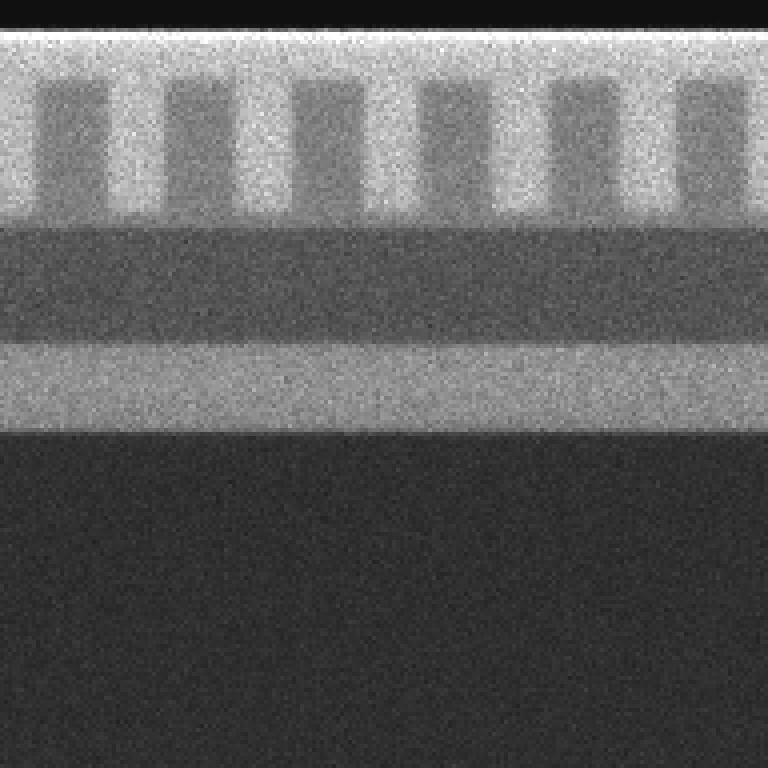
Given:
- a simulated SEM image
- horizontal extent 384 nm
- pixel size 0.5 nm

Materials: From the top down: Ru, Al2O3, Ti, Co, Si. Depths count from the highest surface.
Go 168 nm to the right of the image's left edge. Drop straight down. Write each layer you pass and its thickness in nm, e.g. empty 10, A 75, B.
Ru 24, Al2O3 74, Ti 58, Co 44, Si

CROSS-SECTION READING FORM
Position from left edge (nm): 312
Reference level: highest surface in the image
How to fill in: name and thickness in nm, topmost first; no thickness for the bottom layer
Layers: Ru 90, Al2O3 8, Ti 58, Co 44, Si